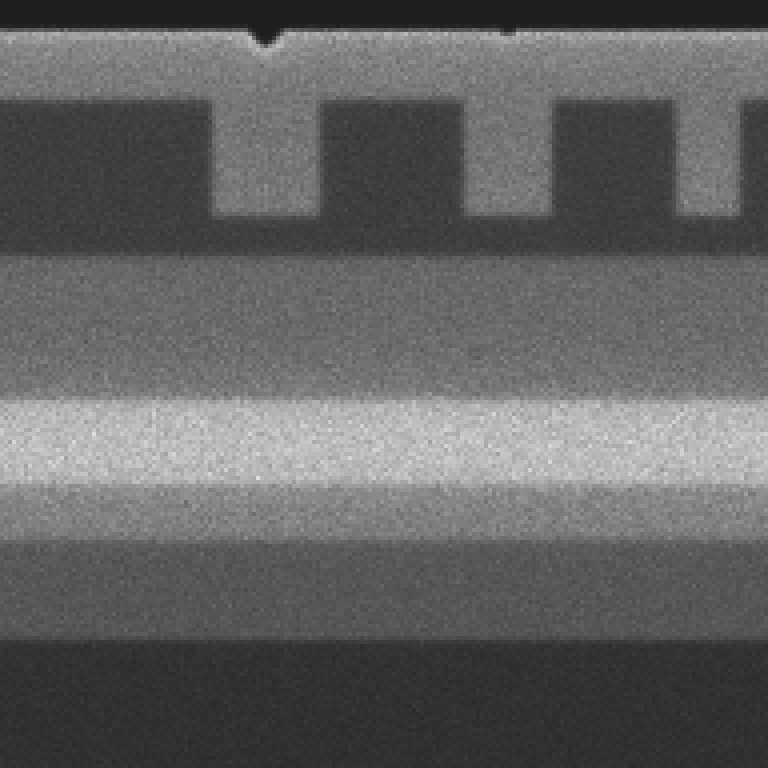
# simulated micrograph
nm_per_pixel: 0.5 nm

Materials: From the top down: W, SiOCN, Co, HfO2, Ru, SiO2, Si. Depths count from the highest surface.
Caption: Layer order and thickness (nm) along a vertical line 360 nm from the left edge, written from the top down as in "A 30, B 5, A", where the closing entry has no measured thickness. W 92, SiOCN 20, Co 72, HfO2 42, Ru 28, SiO2 50, Si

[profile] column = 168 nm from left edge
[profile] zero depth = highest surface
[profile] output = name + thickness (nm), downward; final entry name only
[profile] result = W 34, SiOCN 78, Co 72, HfO2 42, Ru 28, SiO2 50, Si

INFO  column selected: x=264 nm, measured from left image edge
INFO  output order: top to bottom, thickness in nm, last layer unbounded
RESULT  W 92, SiOCN 20, Co 72, HfO2 42, Ru 28, SiO2 50, Si